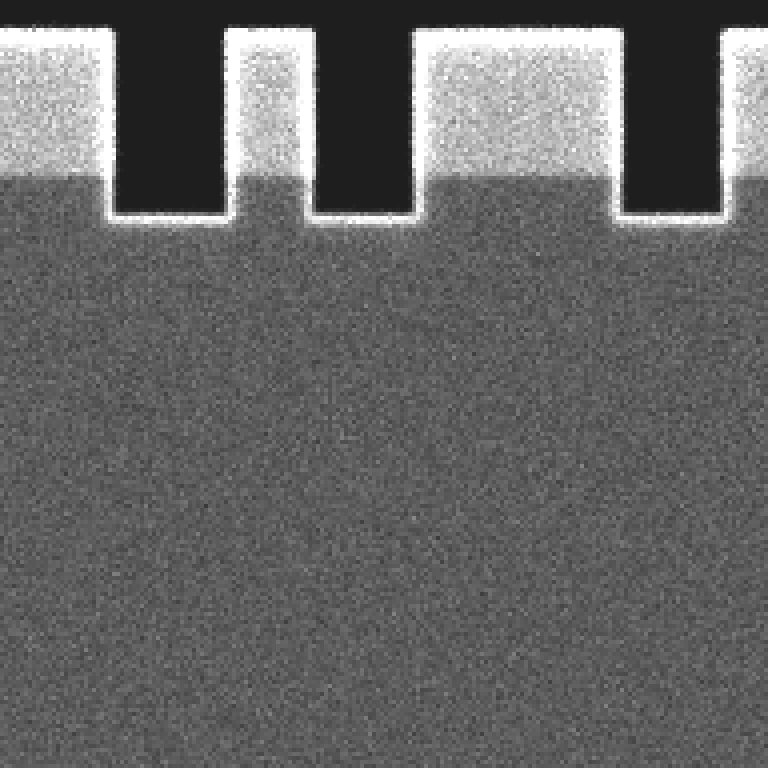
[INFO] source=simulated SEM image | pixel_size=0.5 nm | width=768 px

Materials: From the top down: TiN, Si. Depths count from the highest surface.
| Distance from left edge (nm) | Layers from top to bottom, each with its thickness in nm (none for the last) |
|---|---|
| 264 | TiN 72, Si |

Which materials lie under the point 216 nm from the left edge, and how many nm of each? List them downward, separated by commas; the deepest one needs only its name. TiN 72, Si